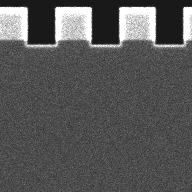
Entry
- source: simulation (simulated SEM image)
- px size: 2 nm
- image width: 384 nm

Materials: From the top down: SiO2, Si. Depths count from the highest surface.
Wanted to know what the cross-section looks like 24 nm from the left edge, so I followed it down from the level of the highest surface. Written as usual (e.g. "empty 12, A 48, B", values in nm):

SiO2 64, Si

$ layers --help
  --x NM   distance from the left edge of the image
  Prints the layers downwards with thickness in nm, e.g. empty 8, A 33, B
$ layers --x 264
SiO2 64, Si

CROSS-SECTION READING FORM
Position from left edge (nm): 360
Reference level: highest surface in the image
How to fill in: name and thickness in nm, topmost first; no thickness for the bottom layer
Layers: empty 74, Si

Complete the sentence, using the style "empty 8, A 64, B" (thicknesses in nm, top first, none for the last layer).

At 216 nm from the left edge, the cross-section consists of empty 74, Si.